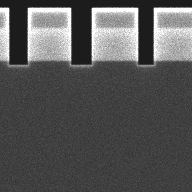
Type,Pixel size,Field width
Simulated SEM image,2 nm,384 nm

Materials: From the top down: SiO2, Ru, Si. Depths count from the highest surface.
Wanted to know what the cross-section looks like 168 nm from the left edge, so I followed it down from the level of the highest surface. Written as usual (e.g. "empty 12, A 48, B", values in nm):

empty 114, Si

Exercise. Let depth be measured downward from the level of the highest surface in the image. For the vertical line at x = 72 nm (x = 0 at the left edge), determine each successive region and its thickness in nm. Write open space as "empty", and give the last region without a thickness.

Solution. SiO2 40, Ru 66, Si